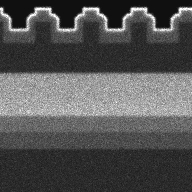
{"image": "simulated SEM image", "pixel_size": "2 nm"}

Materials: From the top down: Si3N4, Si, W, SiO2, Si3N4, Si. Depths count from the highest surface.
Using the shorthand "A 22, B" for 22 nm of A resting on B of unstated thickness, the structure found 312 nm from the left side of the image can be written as empty 42, Si3N4 28, Si 60, W 86, SiO2 32, Si3N4 34, Si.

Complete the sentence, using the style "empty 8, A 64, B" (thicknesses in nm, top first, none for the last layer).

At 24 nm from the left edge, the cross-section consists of empty 42, Si3N4 28, Si 60, W 86, SiO2 32, Si3N4 34, Si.